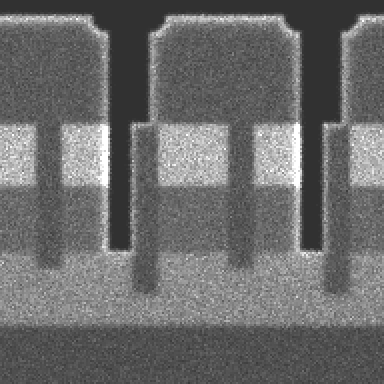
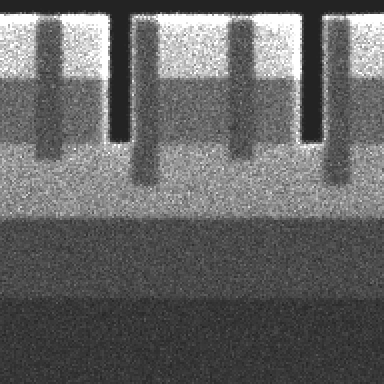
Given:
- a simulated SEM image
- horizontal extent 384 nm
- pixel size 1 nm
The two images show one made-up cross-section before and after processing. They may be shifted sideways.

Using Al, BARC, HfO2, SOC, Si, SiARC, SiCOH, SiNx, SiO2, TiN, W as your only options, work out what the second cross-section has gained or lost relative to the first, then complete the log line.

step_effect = removed SOC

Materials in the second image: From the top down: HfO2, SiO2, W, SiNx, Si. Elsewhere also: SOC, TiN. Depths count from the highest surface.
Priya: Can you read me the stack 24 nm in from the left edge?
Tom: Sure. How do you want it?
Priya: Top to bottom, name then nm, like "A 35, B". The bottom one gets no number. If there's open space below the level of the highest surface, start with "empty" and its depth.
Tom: HfO2 62, SiO2 66, W 74, SiNx 80, Si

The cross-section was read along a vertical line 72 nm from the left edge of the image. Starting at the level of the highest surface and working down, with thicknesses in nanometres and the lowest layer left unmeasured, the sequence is HfO2 62, SiO2 66, W 74, SiNx 80, Si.